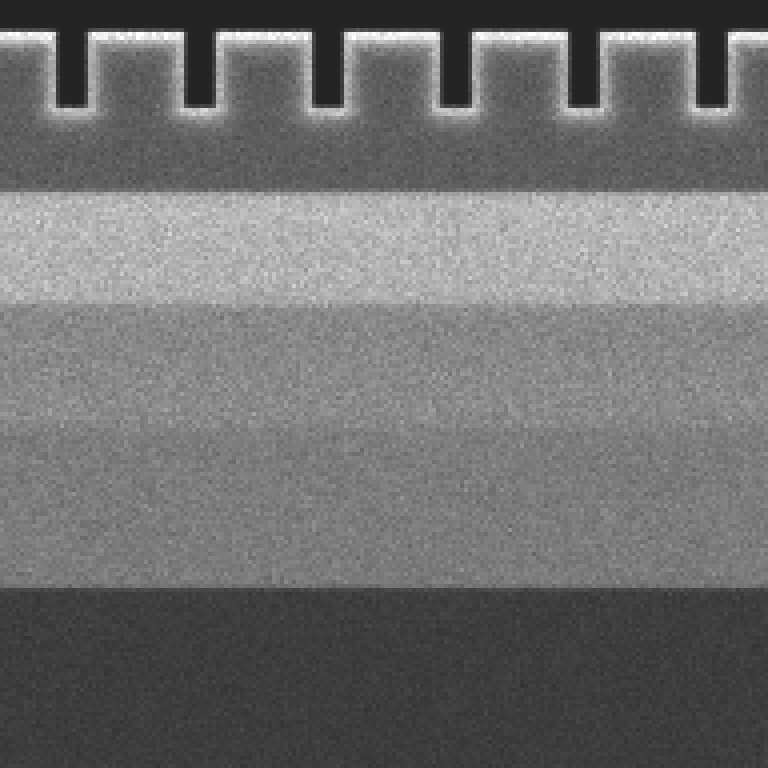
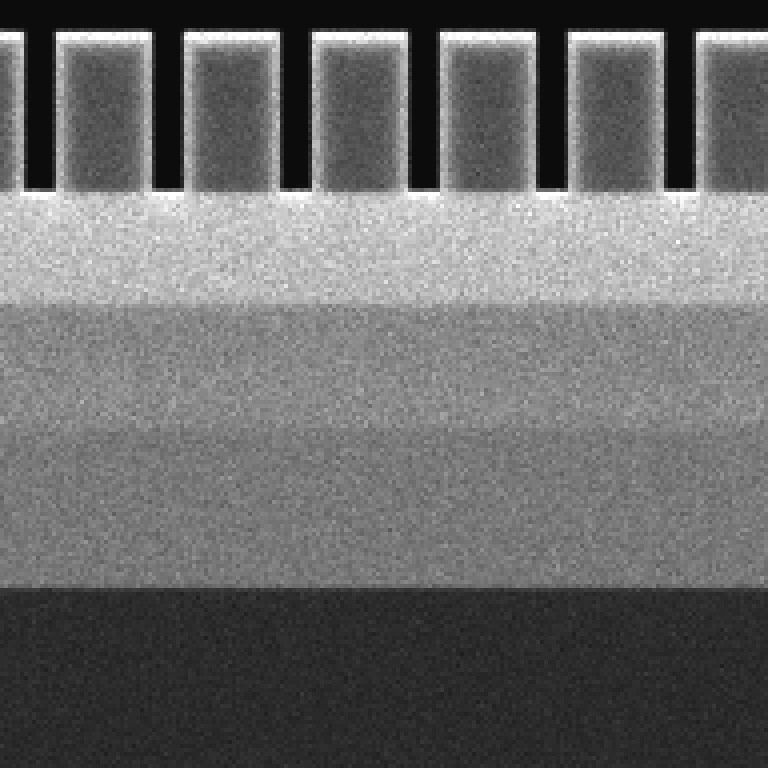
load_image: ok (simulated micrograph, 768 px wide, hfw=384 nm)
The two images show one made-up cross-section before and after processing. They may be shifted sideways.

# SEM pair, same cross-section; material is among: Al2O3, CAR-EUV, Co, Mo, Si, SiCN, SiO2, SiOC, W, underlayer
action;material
removed;underlayer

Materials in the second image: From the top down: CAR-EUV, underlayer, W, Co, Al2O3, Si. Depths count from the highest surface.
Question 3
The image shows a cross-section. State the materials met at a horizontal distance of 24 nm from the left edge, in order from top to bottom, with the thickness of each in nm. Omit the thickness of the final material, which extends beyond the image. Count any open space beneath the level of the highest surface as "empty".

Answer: empty 80, W 56, Co 62, Al2O3 80, Si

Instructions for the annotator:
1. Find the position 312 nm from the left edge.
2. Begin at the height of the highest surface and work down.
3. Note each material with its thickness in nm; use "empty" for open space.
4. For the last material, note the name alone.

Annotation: CAR-EUV 38, underlayer 42, W 56, Co 62, Al2O3 80, Si